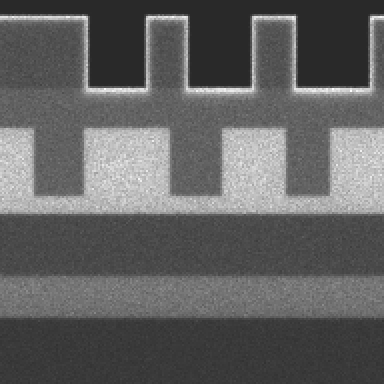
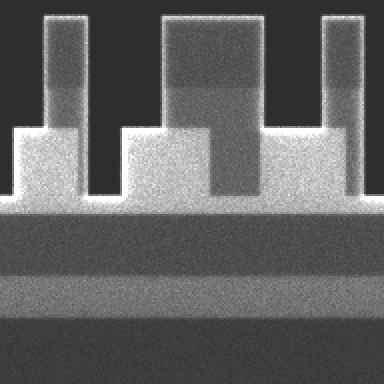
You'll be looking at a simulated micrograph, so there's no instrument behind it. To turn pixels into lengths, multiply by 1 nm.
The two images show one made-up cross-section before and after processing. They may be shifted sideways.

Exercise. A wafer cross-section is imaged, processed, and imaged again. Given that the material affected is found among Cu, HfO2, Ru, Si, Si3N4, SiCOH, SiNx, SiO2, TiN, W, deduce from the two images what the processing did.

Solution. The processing removed SiO2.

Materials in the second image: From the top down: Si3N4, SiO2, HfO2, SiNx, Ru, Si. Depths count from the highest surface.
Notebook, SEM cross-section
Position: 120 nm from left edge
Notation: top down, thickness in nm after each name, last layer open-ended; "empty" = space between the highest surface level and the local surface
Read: empty 180, HfO2 18, SiNx 62, Ru 42, Si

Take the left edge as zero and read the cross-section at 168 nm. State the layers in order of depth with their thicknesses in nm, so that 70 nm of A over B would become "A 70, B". Si3N4 72, SiO2 40, HfO2 86, SiNx 62, Ru 42, Si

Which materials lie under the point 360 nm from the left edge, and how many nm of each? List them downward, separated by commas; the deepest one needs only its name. Si3N4 72, SiO2 108, HfO2 18, SiNx 62, Ru 42, Si